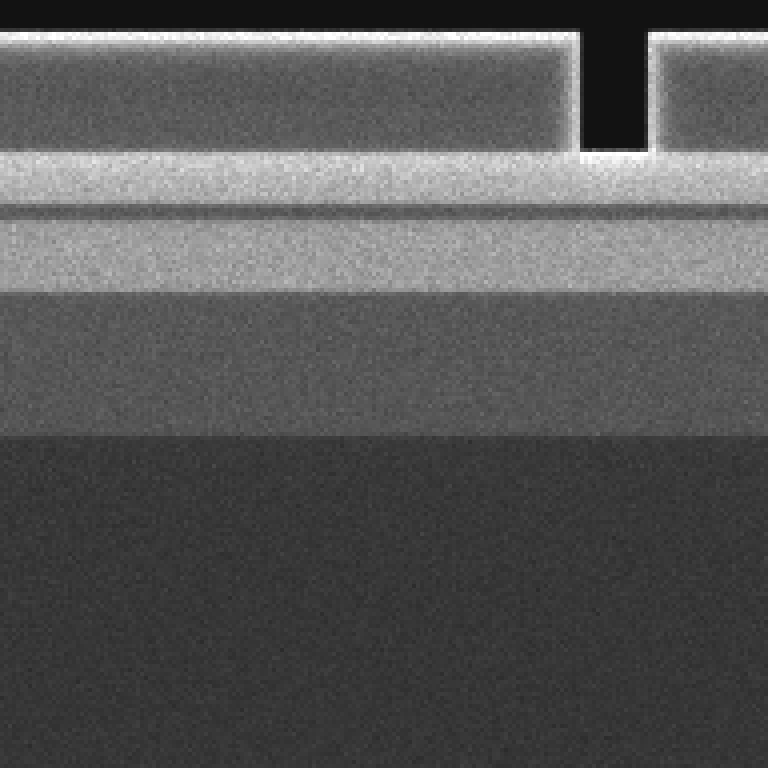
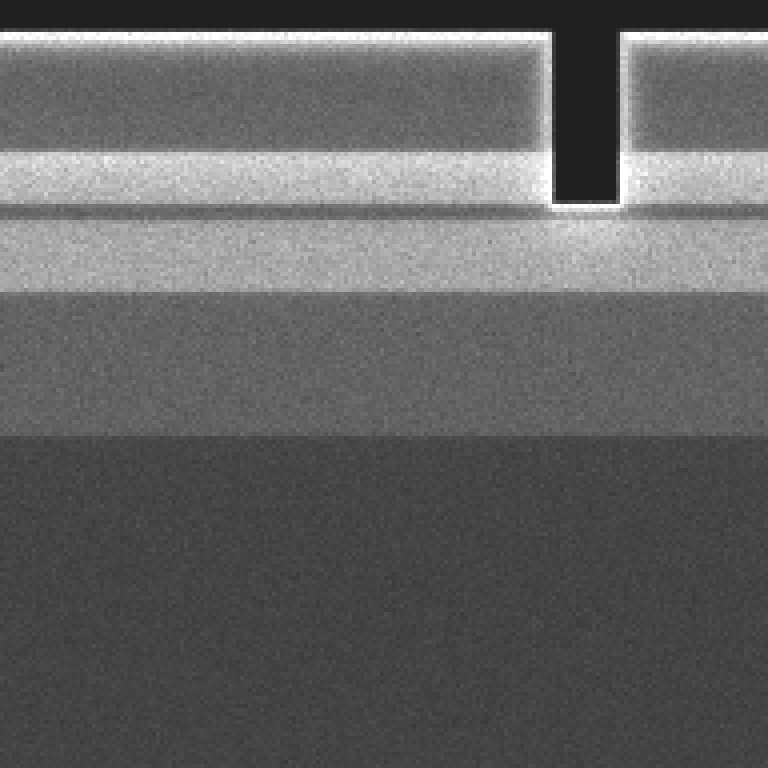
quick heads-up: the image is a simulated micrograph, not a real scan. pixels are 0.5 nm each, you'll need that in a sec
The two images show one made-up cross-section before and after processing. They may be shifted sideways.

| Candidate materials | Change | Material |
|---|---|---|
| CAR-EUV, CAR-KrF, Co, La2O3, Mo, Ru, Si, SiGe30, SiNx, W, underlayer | removed | W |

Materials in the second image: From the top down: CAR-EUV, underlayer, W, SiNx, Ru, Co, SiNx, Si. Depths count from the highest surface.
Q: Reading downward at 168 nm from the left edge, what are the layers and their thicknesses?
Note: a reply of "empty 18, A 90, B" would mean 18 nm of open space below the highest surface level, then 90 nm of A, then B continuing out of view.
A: CAR-EUV 36, underlayer 24, W 26, SiNx 8, Ru 18, Co 18, SiNx 72, Si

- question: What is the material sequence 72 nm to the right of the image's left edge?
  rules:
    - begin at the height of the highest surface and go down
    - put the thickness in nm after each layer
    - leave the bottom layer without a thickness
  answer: CAR-EUV 36, underlayer 24, W 26, SiNx 8, Ru 18, Co 18, SiNx 72, Si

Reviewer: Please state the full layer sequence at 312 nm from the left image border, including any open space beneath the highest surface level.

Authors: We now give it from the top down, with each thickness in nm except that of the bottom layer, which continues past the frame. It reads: CAR-EUV 36, underlayer 24, W 26, SiNx 8, Ru 18, Co 18, SiNx 72, Si